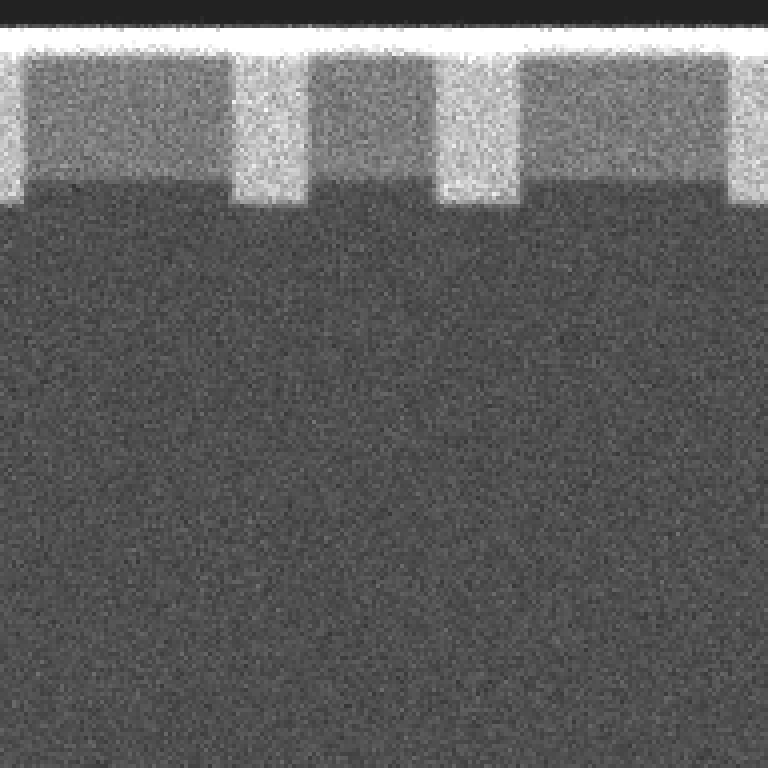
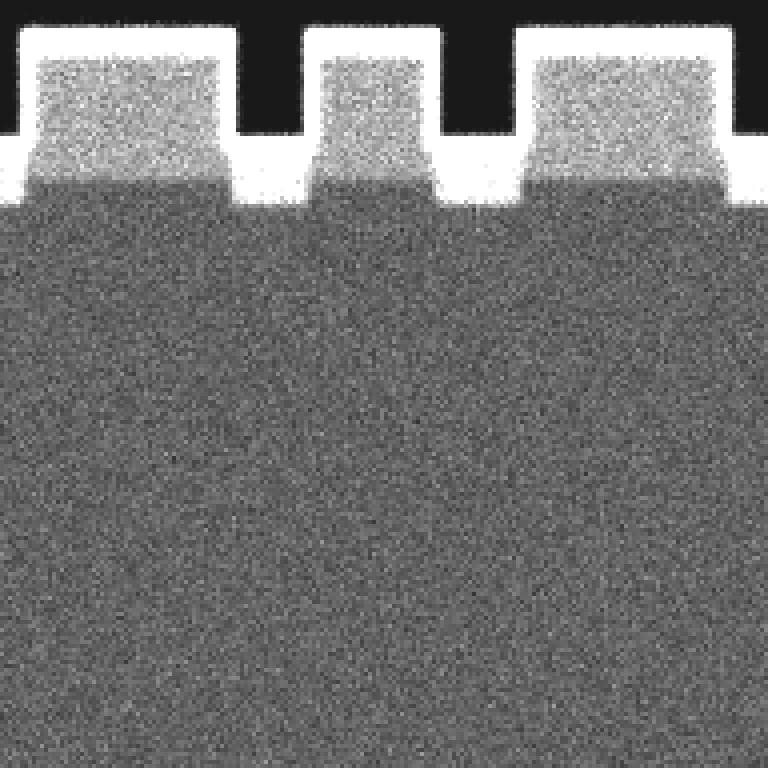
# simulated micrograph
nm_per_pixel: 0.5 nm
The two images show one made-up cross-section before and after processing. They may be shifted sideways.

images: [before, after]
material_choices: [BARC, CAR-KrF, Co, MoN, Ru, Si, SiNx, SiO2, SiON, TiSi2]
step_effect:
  removed: SiO2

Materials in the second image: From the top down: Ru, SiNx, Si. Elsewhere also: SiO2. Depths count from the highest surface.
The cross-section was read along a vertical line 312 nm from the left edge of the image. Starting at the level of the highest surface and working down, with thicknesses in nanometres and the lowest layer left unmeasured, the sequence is Ru 12, SiNx 62, Si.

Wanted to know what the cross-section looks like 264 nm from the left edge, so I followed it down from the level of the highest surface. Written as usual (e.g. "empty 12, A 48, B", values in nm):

Ru 12, SiNx 62, Si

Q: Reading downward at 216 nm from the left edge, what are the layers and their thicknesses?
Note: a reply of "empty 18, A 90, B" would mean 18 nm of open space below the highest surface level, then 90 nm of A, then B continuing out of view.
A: Ru 12, SiNx 62, Si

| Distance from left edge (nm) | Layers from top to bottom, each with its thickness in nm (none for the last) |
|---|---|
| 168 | Ru 12, SiNx 62, Si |